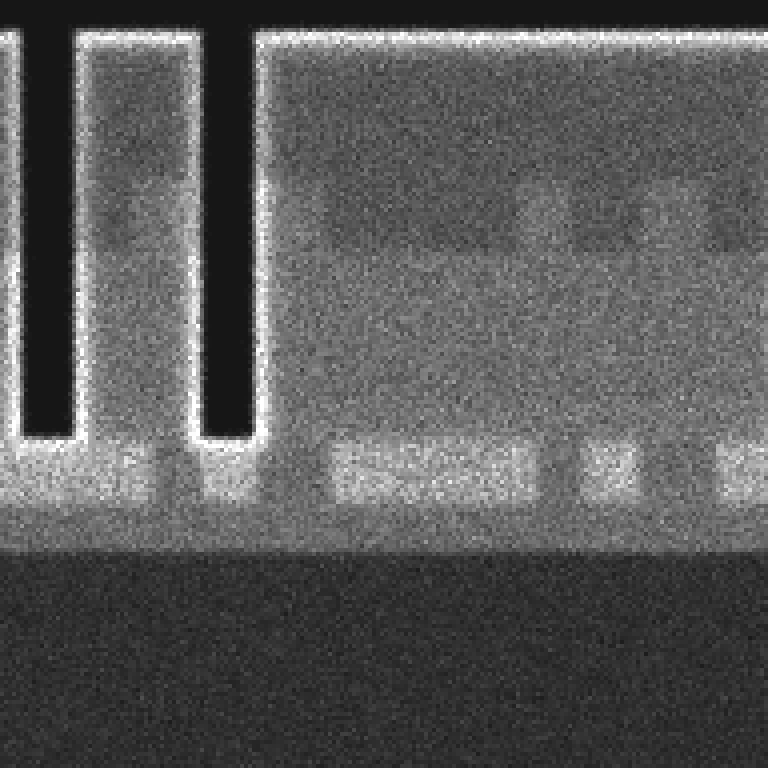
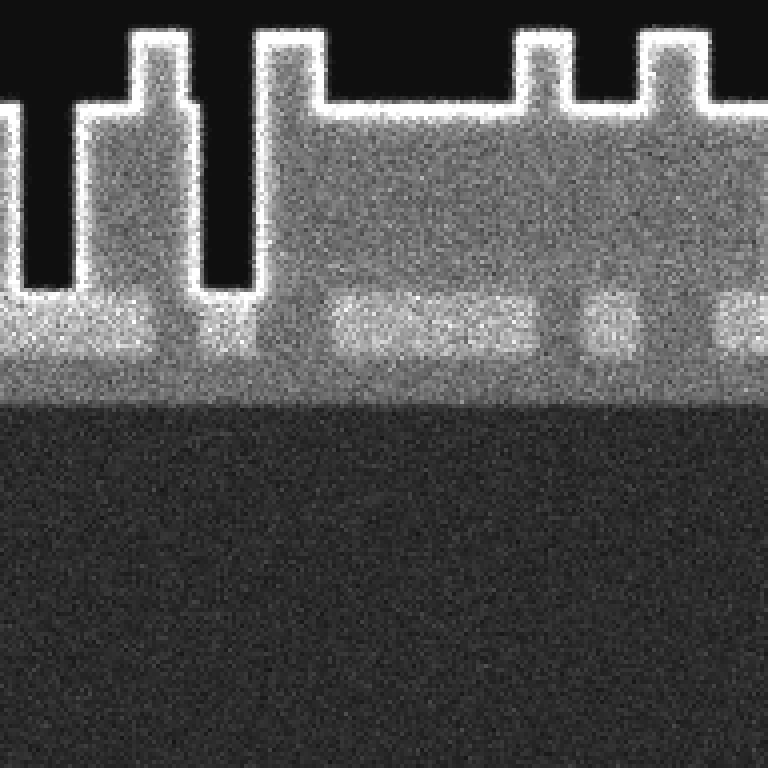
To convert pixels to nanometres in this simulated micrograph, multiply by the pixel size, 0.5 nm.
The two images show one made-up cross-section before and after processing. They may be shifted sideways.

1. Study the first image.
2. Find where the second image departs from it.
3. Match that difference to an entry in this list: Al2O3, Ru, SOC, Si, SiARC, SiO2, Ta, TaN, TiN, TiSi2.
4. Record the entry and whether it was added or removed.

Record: SOC / removed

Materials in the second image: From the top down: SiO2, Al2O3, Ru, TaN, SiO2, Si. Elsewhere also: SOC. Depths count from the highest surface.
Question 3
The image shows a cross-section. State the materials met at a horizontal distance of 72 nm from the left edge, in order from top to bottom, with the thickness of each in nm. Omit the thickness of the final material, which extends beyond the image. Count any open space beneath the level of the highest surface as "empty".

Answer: SiO2 110, Al2O3 20, TaN 32, SiO2 24, Si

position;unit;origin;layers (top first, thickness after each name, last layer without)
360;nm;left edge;empty 36, SiO2 74, Al2O3 20, TaN 32, SiO2 24, Si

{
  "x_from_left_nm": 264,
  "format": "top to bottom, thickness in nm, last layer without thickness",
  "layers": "SiO2 110, Al2O3 20, TaN 32, SiO2 24, Si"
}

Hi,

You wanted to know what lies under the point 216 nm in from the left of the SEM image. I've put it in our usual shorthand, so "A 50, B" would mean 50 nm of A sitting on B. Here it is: empty 36, SiO2 74, Al2O3 20, Ru 22, TaN 10, SiO2 24, Si